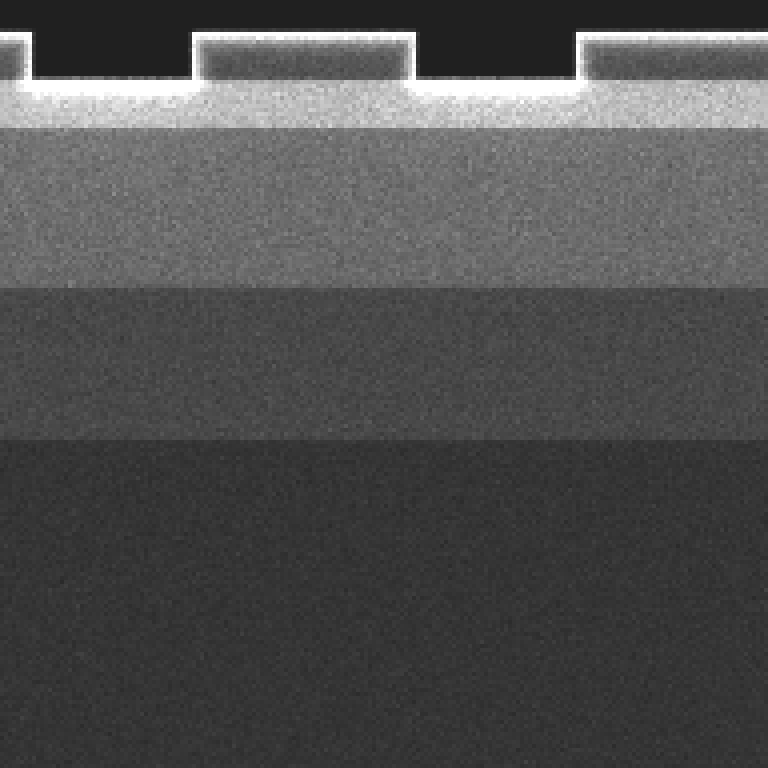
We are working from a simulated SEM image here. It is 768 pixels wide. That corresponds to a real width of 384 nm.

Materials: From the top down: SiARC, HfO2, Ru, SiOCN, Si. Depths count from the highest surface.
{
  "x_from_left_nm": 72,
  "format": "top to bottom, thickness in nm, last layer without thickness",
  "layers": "empty 24, HfO2 24, Ru 80, SiOCN 76, Si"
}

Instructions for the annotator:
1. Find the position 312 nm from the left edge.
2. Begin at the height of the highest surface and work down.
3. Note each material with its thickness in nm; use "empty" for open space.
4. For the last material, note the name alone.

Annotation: SiARC 24, HfO2 24, Ru 80, SiOCN 76, Si